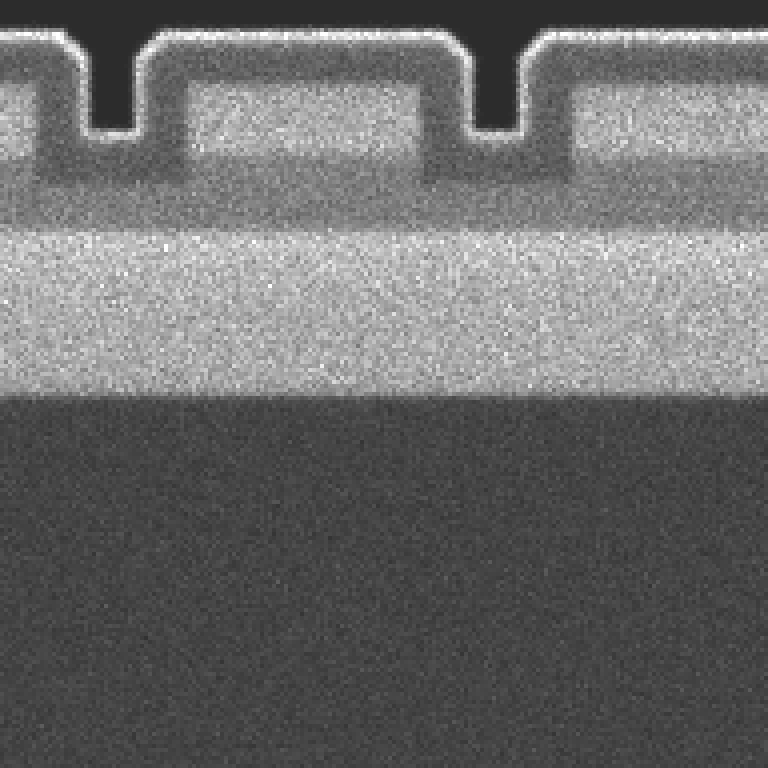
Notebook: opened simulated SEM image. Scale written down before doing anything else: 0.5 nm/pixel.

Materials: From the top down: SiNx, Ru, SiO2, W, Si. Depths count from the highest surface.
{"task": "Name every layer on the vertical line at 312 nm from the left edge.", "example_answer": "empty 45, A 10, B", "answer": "SiNx 26, Ru 36, SiO2 38, W 82, Si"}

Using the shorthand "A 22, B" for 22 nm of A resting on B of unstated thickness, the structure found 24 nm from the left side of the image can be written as SiNx 76, SiO2 24, W 82, Si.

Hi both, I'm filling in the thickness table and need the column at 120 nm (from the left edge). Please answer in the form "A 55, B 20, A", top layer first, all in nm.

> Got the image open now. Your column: SiNx 26, Ru 36, SiO2 38, W 82, Si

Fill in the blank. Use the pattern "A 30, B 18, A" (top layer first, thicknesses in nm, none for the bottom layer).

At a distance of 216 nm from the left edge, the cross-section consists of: SiNx 76, SiO2 24, W 82, Si